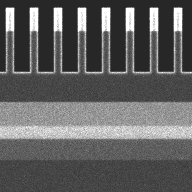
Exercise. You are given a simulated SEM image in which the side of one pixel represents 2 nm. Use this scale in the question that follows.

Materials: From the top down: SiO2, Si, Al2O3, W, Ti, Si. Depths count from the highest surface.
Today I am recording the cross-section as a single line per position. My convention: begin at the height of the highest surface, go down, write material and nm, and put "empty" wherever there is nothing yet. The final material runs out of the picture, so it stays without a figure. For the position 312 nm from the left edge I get SiO2 46, Si 142, Al2O3 48, W 26, Ti 42, Si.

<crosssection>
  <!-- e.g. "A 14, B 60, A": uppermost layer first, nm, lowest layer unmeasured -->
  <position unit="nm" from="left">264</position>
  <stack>SiO2 46, Si 142, Al2O3 48, W 26, Ti 42, Si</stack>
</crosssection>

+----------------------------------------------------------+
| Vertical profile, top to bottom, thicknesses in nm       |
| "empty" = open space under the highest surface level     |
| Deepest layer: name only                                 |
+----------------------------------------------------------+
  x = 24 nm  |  SiO2 46, Si 142, Al2O3 48, W 26, Ti 42, Si